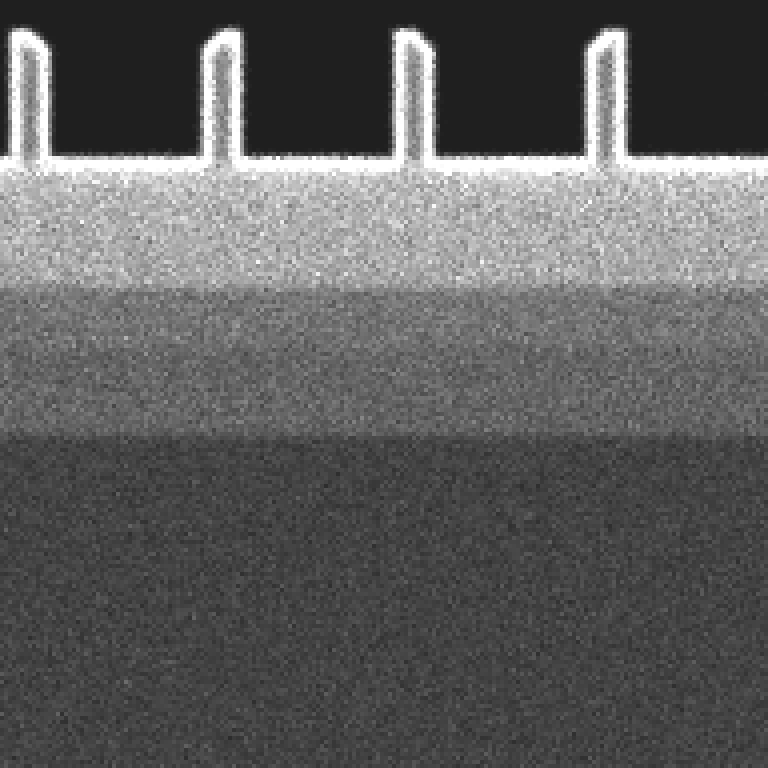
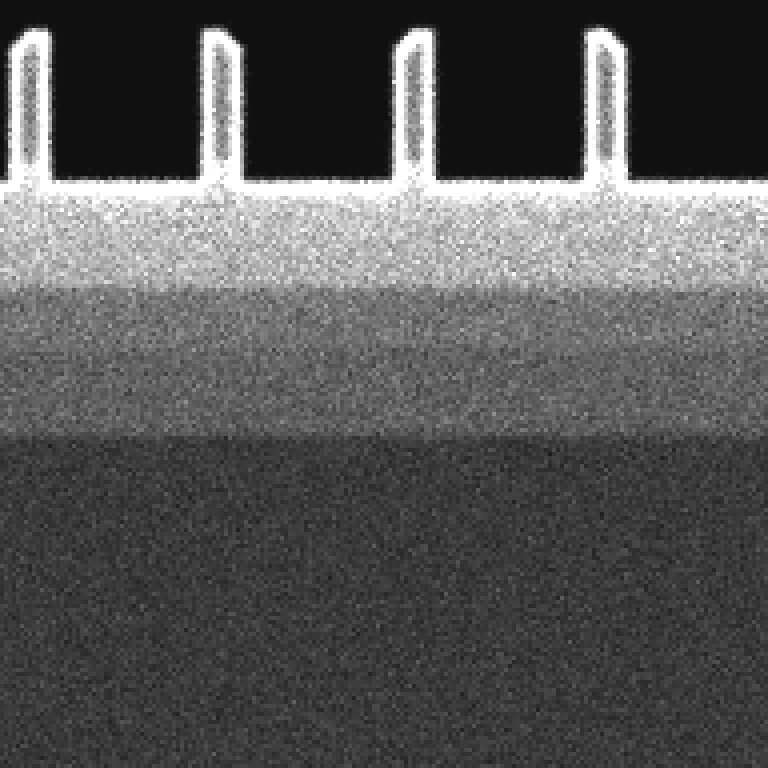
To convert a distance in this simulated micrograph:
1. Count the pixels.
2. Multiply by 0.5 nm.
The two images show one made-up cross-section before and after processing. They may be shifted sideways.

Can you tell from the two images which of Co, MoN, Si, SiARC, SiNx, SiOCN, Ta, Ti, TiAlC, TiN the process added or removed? Yes, it removed Co.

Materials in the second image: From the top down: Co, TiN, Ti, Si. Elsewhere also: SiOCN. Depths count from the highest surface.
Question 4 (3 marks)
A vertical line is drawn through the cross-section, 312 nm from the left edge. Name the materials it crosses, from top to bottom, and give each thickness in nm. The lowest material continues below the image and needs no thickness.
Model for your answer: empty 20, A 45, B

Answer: empty 76, Co 52, TiN 30, Ti 44, Si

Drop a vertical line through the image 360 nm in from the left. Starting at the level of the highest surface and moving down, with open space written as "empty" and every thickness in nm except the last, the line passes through empty 76, Co 52, TiN 30, Ti 44, Si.